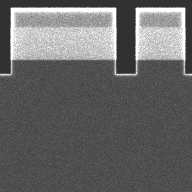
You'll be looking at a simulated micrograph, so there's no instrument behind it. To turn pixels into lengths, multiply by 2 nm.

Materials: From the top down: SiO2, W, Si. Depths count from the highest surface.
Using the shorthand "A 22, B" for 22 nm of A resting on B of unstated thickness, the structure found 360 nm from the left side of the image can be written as SiO2 38, W 66, Si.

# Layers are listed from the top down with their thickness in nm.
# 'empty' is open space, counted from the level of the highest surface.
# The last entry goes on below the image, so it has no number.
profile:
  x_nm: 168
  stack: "SiO2 38, W 66, Si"